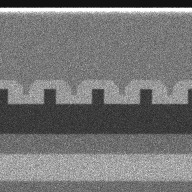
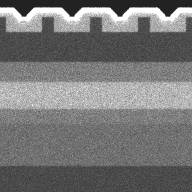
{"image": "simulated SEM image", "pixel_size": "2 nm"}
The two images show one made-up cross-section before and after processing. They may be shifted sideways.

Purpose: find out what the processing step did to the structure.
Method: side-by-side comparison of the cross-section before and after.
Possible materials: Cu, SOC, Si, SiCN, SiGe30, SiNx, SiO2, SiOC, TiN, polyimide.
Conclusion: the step removed SOC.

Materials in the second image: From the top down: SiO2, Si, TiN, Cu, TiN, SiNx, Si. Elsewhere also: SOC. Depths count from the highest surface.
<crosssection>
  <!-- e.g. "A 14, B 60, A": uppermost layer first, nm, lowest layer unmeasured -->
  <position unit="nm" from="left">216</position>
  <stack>SiO2 48, Si 60, TiN 40, Cu 54, TiN 30, SiNx 84, Si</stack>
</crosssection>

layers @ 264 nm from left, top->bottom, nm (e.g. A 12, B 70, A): SiO2 48, Si 60, TiN 40, Cu 54, TiN 30, SiNx 84, Si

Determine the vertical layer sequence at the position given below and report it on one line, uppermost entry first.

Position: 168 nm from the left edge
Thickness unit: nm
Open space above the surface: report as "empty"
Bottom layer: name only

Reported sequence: SiO2 48, Si 60, TiN 40, Cu 54, TiN 30, SiNx 84, Si